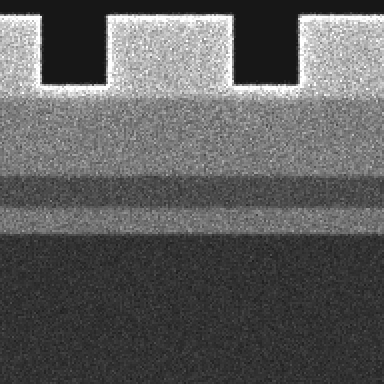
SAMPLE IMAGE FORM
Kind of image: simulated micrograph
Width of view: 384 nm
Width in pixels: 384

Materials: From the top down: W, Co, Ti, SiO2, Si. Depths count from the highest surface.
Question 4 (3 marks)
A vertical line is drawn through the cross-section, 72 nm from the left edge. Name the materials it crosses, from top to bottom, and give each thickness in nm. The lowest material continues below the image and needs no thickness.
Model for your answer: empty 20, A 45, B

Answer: empty 70, W 12, Co 78, Ti 32, SiO2 26, Si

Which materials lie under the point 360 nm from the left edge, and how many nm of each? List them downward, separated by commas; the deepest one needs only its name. W 82, Co 78, Ti 32, SiO2 26, Si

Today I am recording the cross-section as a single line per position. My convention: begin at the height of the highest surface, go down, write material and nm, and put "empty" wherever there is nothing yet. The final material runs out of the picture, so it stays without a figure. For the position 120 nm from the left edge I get W 82, Co 78, Ti 32, SiO2 26, Si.